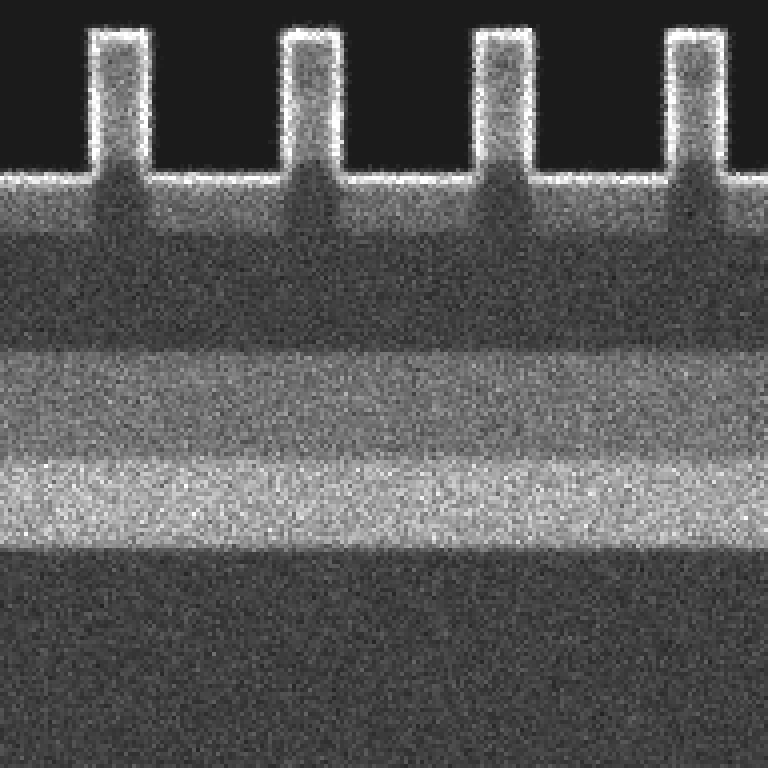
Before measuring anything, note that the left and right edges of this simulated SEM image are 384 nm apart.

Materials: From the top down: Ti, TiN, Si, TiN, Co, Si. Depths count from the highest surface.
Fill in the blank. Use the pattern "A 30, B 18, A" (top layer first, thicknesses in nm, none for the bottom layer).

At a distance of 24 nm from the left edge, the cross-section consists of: empty 72, Ti 28, Si 60, TiN 54, Co 44, Si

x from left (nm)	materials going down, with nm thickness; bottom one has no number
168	Ti 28, TiN 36, Si 96, TiN 54, Co 44, Si